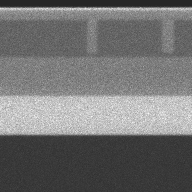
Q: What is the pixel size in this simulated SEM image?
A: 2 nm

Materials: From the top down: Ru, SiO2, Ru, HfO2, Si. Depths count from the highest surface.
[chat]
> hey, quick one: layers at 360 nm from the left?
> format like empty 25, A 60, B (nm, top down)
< Ru 24, SiO2 74, Ru 78, HfO2 78, Si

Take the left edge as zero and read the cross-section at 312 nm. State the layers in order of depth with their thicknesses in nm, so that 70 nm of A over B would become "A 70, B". Ru 24, SiO2 74, Ru 78, HfO2 78, Si